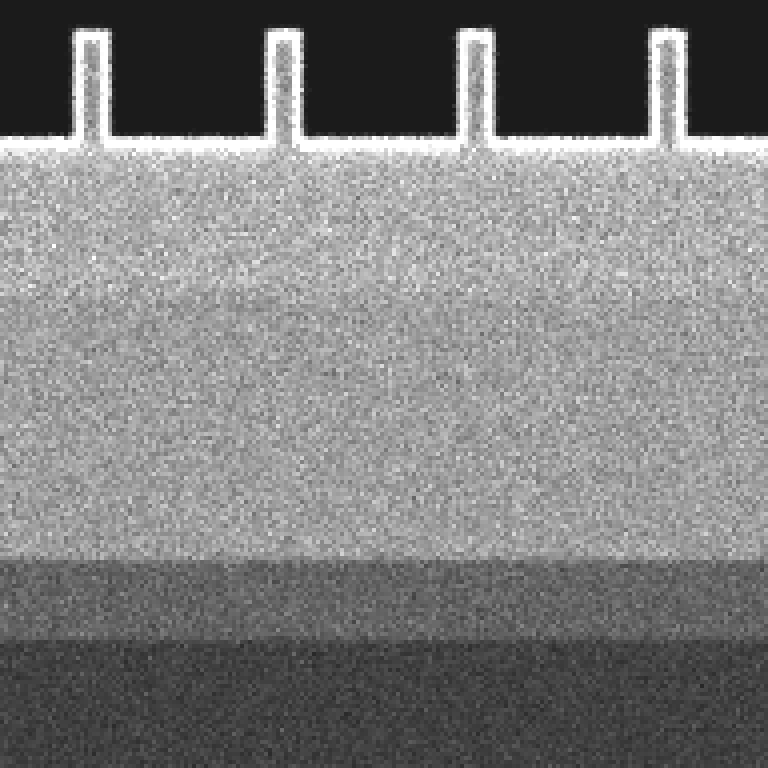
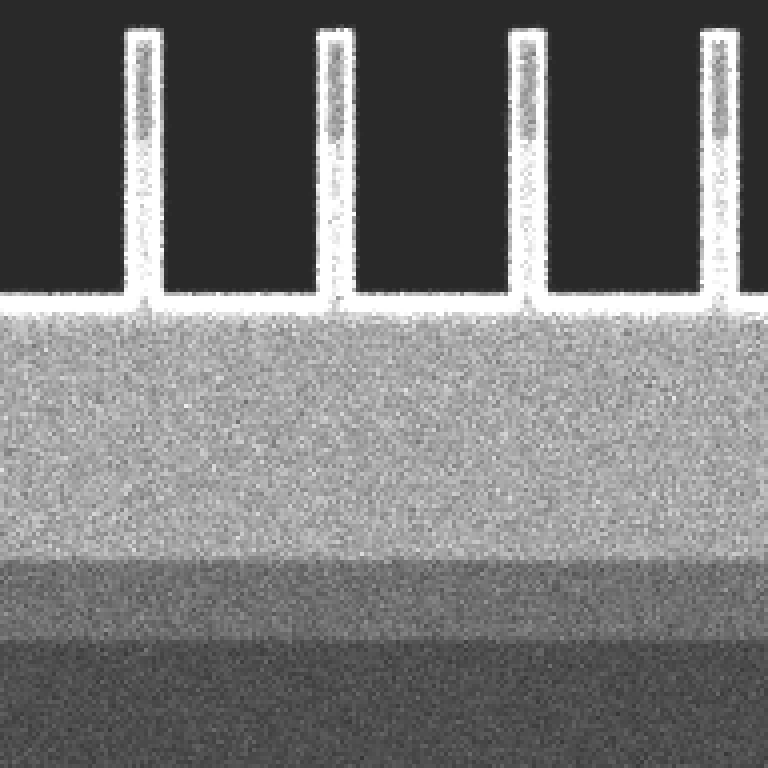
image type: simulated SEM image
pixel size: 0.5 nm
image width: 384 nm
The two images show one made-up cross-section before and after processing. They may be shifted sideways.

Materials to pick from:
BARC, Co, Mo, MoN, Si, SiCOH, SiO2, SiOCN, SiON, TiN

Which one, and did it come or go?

Co - removed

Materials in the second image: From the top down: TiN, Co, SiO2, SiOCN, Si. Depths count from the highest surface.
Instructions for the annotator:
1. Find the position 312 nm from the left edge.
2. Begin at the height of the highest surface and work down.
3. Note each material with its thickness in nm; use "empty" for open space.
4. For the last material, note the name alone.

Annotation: empty 132, SiO2 132, SiOCN 40, Si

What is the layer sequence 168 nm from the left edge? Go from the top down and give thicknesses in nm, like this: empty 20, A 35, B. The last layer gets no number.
TiN 54, Co 78, SiO2 132, SiOCN 40, Si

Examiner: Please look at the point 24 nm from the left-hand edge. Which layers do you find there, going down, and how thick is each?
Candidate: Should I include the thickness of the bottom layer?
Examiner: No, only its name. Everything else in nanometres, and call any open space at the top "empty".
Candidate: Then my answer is empty 132, SiO2 132, SiOCN 40, Si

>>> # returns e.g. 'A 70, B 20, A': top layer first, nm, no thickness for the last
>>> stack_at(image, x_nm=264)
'TiN 54, Co 78, SiO2 132, SiOCN 40, Si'